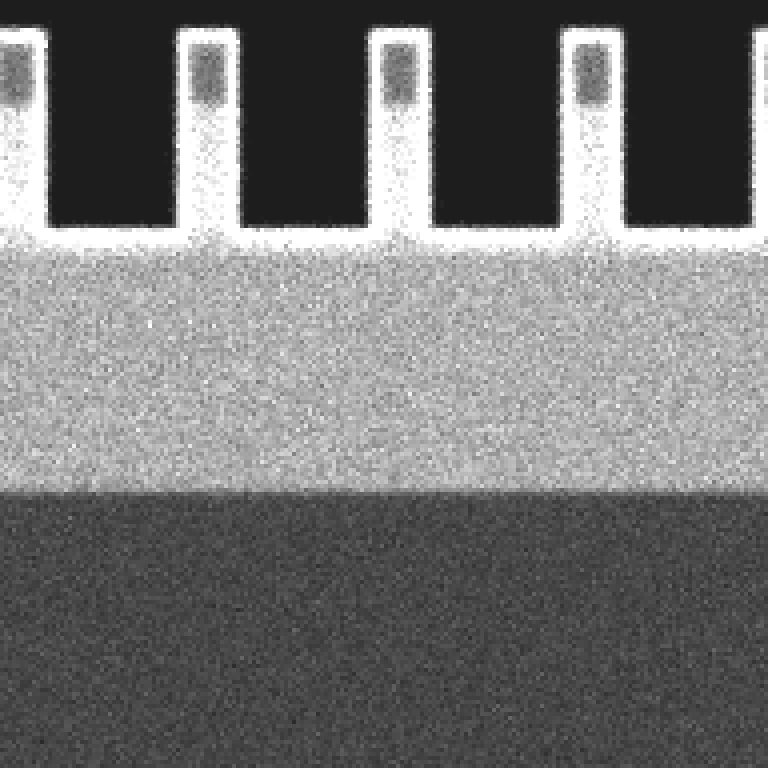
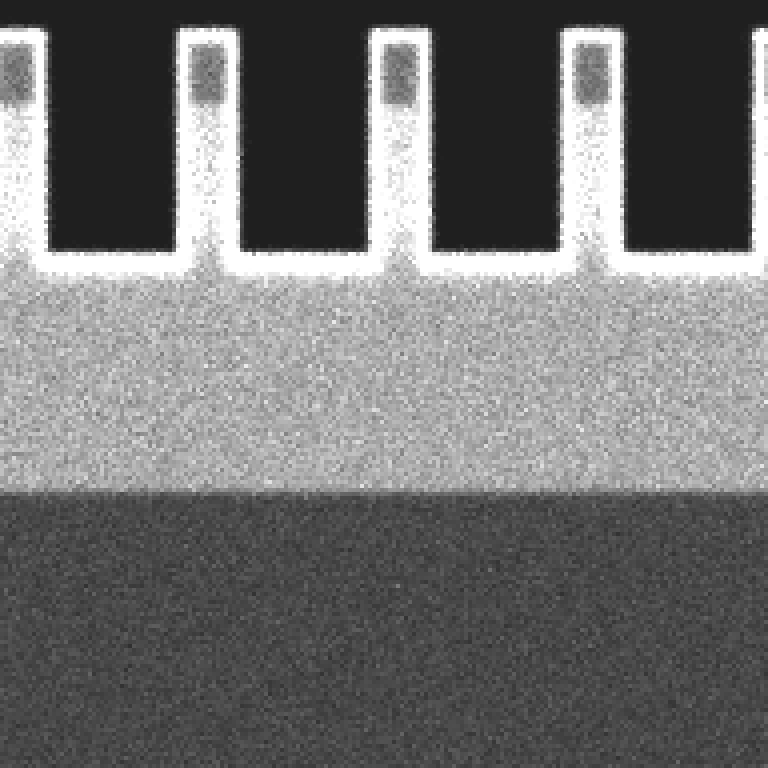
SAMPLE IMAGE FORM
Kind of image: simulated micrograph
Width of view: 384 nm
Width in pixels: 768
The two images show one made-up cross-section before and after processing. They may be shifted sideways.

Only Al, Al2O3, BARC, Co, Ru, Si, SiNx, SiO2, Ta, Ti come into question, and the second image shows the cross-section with Co removed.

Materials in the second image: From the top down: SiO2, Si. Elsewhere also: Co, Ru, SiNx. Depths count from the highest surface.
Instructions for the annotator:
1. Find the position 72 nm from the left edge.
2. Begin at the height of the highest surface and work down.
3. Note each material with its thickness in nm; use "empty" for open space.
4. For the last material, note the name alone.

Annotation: empty 112, SiO2 118, Si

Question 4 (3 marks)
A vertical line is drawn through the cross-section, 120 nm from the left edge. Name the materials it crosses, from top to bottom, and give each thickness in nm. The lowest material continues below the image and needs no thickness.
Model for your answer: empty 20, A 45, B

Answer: empty 112, SiO2 118, Si